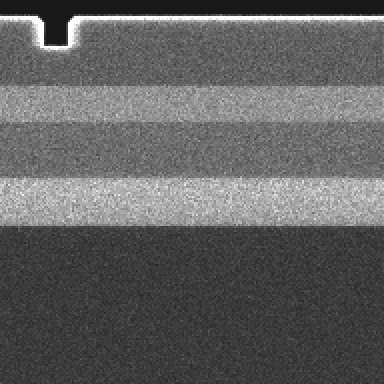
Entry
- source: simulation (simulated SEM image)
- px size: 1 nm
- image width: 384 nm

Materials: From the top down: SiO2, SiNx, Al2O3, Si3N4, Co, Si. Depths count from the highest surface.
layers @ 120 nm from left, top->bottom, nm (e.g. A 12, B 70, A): SiNx 70, Al2O3 36, Si3N4 56, Co 48, Si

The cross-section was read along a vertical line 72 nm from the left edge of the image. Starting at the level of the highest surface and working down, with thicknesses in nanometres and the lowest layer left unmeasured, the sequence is empty 2, SiO2 28, SiNx 40, Al2O3 36, Si3N4 56, Co 48, Si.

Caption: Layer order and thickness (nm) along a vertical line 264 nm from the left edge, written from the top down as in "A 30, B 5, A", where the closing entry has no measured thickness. SiNx 70, Al2O3 36, Si3N4 56, Co 48, Si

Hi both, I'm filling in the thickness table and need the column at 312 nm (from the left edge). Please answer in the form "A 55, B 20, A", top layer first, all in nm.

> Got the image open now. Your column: SiNx 70, Al2O3 36, Si3N4 56, Co 48, Si